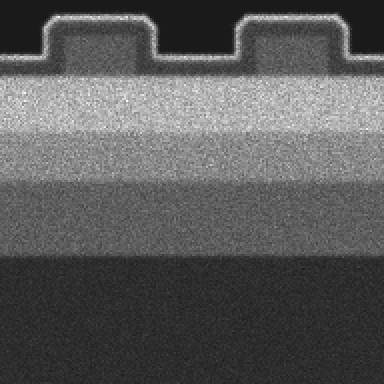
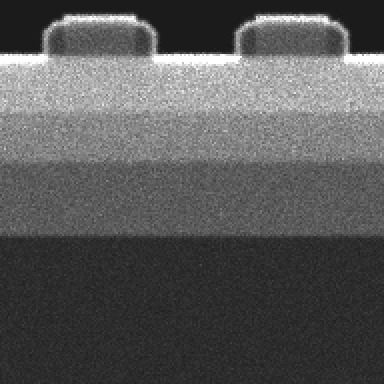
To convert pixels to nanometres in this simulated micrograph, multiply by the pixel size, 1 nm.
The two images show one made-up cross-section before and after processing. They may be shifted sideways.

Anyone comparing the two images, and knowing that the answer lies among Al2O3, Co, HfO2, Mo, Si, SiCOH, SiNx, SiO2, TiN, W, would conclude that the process removed SiNx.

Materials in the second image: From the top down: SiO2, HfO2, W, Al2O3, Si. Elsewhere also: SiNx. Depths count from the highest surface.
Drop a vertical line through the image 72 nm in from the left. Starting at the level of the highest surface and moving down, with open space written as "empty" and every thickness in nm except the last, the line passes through SiO2 40, HfO2 56, W 50, Al2O3 74, Si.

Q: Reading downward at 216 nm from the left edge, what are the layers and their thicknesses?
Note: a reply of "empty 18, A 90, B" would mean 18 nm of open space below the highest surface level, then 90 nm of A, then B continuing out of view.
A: empty 40, HfO2 56, W 50, Al2O3 74, Si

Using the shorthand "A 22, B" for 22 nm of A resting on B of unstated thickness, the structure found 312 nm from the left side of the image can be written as SiO2 40, HfO2 56, W 50, Al2O3 74, Si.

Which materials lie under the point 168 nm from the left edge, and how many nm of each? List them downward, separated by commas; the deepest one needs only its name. empty 40, HfO2 56, W 50, Al2O3 74, Si